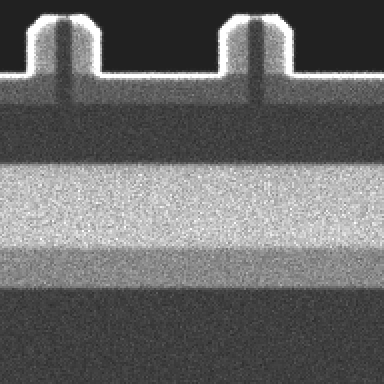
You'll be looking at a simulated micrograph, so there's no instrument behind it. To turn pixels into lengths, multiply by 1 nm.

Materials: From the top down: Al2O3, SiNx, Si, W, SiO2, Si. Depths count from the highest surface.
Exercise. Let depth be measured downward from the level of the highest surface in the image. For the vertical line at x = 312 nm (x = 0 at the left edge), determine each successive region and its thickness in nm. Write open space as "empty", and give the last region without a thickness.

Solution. empty 58, SiNx 30, Si 60, W 84, SiO2 40, Si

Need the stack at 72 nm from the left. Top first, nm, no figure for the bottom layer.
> Al2O3 58, SiNx 30, Si 60, W 84, SiO2 40, Si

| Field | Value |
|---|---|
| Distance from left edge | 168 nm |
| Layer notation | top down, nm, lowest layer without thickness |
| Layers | empty 58, SiNx 30, Si 60, W 84, SiO2 40, Si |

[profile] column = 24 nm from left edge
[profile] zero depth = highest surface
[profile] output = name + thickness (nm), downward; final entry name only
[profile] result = empty 58, SiNx 30, Si 60, W 84, SiO2 40, Si